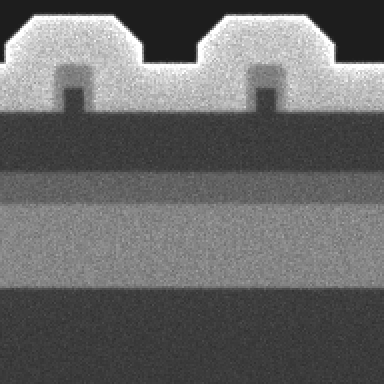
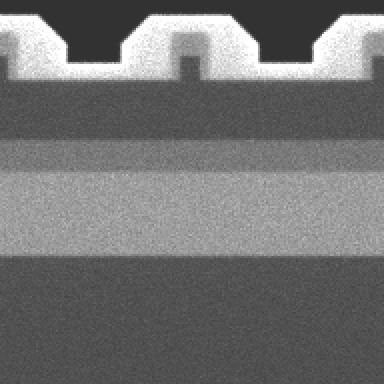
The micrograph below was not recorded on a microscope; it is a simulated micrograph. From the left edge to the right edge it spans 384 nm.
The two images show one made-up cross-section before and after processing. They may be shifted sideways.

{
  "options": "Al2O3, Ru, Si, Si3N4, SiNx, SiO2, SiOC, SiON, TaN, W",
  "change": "removed",
  "material": "W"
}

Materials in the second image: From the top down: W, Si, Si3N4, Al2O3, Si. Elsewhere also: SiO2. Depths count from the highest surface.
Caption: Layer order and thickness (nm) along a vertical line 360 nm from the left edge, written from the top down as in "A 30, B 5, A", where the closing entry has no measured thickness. W 64, Si 60, Si3N4 32, Al2O3 84, Si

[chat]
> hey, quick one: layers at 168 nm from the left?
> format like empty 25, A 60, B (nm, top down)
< W 64, Si 60, Si3N4 32, Al2O3 84, Si